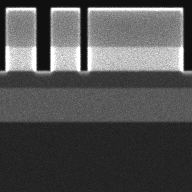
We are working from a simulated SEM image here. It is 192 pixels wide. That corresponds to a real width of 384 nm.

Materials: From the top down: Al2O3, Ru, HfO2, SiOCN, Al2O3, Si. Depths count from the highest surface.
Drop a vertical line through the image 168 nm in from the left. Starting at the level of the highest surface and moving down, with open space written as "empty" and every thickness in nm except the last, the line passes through empty 126, SiOCN 34, Al2O3 68, Si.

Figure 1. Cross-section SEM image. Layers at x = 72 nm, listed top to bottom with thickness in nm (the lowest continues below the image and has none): empty 126, SiOCN 34, Al2O3 68, Si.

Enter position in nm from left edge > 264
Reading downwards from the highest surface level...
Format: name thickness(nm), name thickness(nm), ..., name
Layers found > Al2O3 10, Ru 68, HfO2 48, SiOCN 34, Al2O3 68, Si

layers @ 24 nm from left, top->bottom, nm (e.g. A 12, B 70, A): Al2O3 10, Ru 68, HfO2 48, SiOCN 34, Al2O3 68, Si